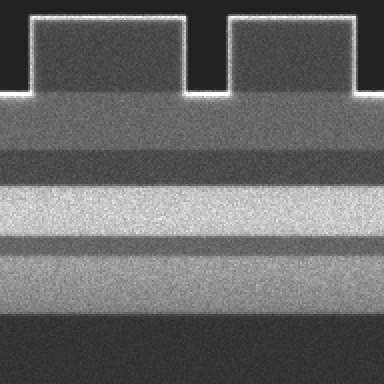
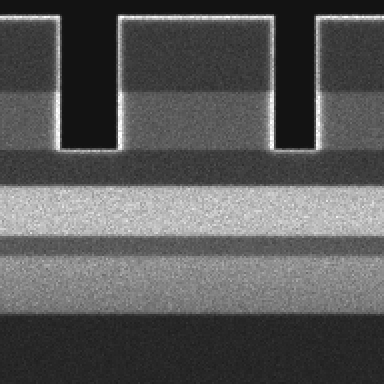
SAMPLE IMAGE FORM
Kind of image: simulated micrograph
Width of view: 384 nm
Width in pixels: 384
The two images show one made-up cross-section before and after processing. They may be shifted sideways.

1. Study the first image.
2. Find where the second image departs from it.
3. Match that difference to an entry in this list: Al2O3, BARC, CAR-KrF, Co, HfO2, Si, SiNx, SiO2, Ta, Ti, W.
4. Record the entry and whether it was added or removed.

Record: Al2O3 / removed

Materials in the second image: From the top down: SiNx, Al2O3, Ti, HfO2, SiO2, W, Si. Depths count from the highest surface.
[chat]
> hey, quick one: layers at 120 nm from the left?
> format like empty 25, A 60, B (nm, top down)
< SiNx 76, Al2O3 58, Ti 36, HfO2 50, SiO2 20, W 58, Si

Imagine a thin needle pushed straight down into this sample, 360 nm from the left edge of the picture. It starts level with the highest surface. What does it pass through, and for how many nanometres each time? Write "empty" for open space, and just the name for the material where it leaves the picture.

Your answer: SiNx 76, Al2O3 58, Ti 36, HfO2 50, SiO2 20, W 58, Si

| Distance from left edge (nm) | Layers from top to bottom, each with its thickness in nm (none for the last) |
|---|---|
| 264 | SiNx 76, Al2O3 58, Ti 36, HfO2 50, SiO2 20, W 58, Si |